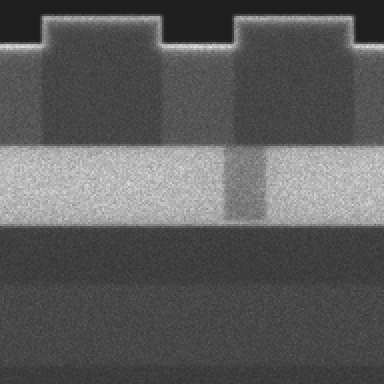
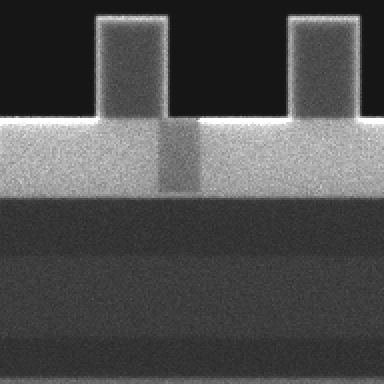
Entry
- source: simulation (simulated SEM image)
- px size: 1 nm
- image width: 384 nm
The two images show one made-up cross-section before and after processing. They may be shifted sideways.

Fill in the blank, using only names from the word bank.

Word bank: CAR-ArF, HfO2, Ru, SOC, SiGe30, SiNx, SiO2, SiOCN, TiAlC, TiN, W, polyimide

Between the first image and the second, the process removed SOC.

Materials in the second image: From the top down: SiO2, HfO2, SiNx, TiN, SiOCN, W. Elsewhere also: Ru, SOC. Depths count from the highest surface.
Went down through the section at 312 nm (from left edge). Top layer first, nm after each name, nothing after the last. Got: SiO2 102, HfO2 80, SiNx 58, TiN 82, SiOCN 40, W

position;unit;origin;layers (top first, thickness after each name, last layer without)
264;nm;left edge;empty 102, HfO2 80, SiNx 58, TiN 82, SiOCN 40, W